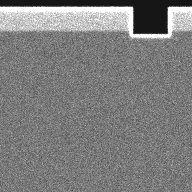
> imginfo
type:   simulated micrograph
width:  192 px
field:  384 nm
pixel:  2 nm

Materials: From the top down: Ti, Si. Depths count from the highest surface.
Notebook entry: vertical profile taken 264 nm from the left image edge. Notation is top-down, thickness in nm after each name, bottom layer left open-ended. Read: empty 54, Si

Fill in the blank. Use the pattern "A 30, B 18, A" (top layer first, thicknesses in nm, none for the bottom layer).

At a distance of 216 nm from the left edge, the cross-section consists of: Ti 46, Si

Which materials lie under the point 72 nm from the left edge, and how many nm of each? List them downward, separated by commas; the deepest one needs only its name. Ti 46, Si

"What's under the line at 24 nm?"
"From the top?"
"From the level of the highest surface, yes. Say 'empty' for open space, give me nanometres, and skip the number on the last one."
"Ti 46, Si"